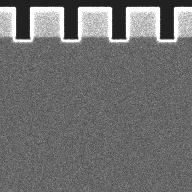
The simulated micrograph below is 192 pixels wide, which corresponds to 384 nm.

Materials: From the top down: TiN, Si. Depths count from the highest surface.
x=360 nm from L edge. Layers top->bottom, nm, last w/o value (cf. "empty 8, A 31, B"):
TiN 58, Si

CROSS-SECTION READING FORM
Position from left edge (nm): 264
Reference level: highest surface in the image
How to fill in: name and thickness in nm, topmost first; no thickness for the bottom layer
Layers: TiN 58, Si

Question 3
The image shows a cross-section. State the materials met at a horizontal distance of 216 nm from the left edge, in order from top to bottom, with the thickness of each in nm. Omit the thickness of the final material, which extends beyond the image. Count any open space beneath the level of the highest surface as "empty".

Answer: TiN 58, Si